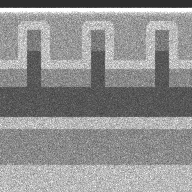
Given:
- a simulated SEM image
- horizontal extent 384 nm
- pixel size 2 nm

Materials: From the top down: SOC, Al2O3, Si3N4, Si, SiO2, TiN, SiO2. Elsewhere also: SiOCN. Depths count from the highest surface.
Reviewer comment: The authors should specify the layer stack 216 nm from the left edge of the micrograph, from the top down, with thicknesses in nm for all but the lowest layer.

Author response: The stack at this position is SOC 26, Al2O3 96, Si3N4 36, Si 60, SiO2 24, TiN 72, SiO2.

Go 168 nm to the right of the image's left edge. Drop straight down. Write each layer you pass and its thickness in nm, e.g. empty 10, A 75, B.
SOC 30, Al2O3 92, Si3N4 36, Si 60, SiO2 24, TiN 72, SiO2